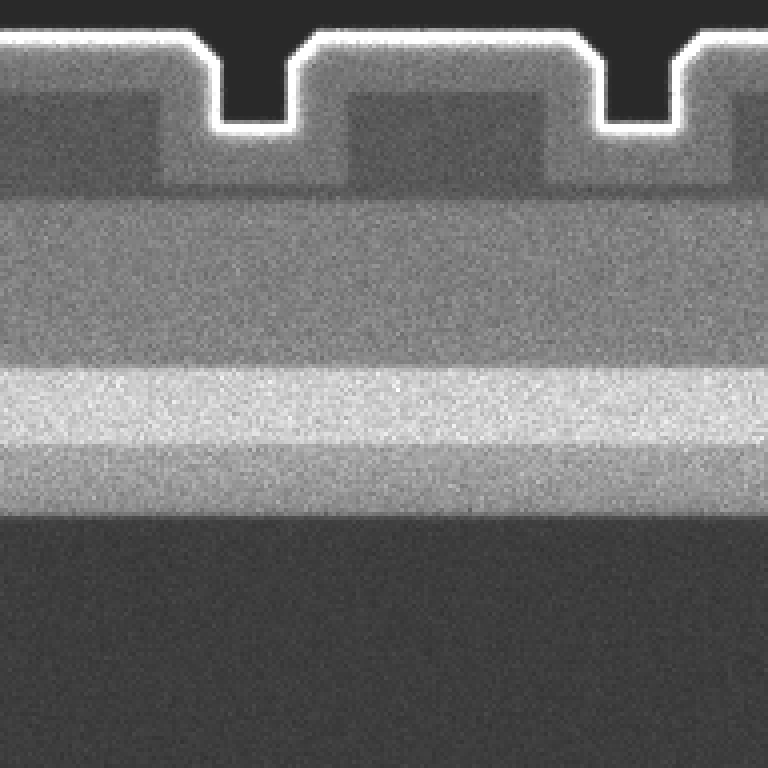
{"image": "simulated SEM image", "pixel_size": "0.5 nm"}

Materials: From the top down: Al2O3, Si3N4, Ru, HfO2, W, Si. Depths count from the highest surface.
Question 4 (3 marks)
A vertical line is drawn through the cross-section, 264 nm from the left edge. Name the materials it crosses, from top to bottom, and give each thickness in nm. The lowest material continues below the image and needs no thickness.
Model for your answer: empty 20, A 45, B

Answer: Al2O3 30, Si3N4 54, Ru 84, HfO2 38, W 36, Si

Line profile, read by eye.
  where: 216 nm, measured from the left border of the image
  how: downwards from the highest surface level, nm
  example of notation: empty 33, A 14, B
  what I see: Al2O3 30, Si3N4 54, Ru 84, HfO2 38, W 36, Si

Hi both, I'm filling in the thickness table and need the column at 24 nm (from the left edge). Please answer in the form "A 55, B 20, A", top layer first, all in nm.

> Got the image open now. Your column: Al2O3 30, Si3N4 54, Ru 84, HfO2 38, W 36, Si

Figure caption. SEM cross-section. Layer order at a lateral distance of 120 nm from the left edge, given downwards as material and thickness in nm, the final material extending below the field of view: empty 46, Al2O3 30, Si3N4 8, Ru 84, HfO2 38, W 36, Si